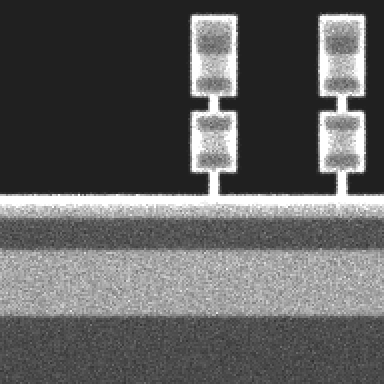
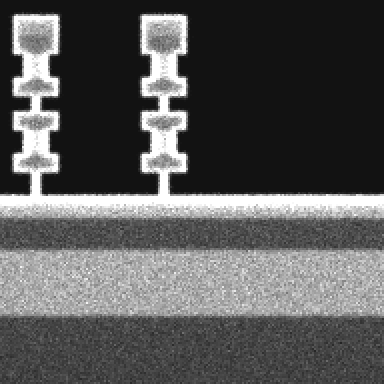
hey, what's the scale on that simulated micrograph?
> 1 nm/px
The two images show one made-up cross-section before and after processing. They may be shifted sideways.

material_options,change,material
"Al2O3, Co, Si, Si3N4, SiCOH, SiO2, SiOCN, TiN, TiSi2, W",removed,Al2O3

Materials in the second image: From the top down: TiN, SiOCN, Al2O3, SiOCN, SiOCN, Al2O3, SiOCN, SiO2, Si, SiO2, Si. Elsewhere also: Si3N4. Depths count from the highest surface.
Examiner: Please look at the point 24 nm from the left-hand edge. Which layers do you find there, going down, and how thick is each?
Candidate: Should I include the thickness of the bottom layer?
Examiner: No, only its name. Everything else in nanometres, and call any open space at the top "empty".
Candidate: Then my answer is TiN 20, SiOCN 18, Al2O3 24, SiOCN 18, empty 16, SiOCN 18, Al2O3 24, SiOCN 18, empty 24, SiO2 22, Si 32, SiO2 66, Si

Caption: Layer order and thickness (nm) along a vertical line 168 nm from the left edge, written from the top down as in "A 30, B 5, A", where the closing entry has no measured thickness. TiN 20, SiOCN 18, Al2O3 24, SiOCN 18, empty 16, SiOCN 18, Al2O3 24, SiOCN 18, empty 24, SiO2 22, Si 32, SiO2 66, Si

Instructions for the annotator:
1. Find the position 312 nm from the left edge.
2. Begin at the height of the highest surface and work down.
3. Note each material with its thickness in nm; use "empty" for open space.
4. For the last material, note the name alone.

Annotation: empty 180, SiO2 22, Si 32, SiO2 66, Si